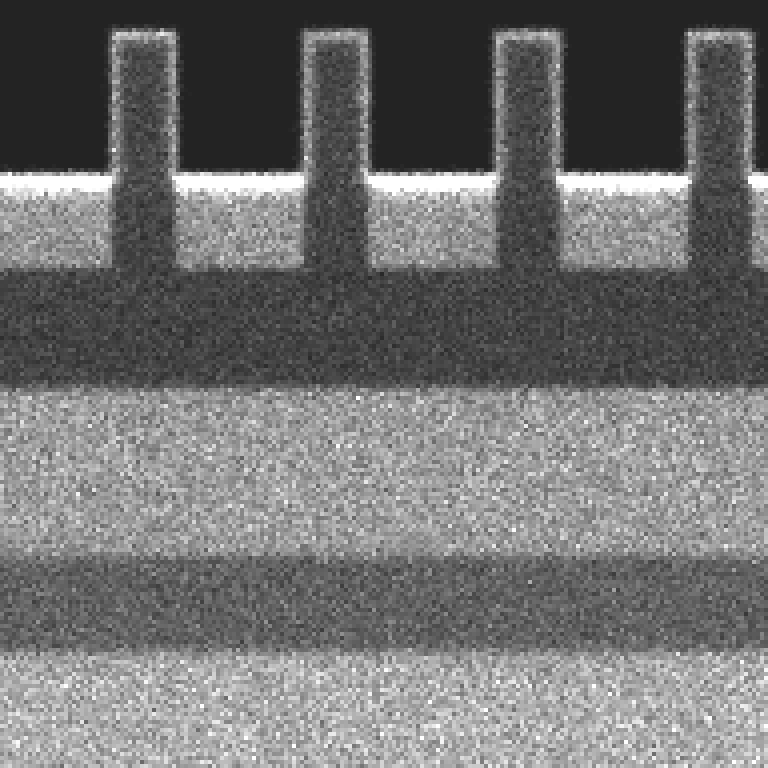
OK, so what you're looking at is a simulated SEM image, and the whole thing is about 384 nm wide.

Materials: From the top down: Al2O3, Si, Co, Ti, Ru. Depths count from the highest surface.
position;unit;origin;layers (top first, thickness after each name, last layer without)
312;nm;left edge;empty 72, Al2O3 46, Si 60, Co 84, Ti 48, Ru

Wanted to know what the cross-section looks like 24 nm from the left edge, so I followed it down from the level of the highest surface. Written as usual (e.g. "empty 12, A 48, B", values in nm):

empty 72, Al2O3 46, Si 60, Co 84, Ti 48, Ru